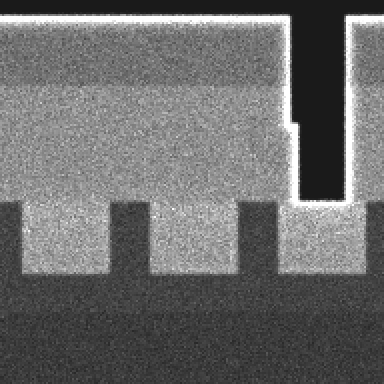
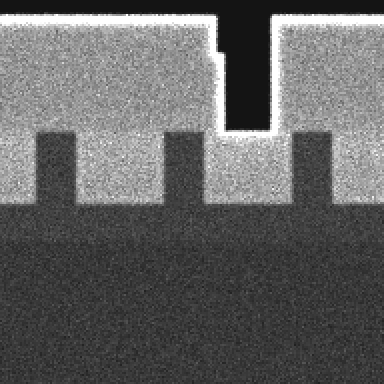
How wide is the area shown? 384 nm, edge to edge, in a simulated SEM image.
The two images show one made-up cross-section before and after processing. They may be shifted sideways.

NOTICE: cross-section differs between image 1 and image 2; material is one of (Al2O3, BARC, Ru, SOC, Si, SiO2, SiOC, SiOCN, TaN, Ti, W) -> removed: SOC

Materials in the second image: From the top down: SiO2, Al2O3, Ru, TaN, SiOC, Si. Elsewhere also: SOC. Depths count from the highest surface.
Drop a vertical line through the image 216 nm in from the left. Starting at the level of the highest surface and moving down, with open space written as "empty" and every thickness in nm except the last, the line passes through empty 38, SiO2 58, Al2O3 20, Ru 64, TaN 8, SiOC 38, Si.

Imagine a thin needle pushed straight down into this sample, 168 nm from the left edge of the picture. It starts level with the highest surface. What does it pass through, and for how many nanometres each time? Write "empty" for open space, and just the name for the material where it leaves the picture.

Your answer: SiO2 96, Al2O3 20, SiOC 110, Si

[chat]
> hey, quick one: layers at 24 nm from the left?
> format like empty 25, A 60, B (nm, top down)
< SiO2 96, Al2O3 20, Ru 64, TaN 8, SiOC 38, Si